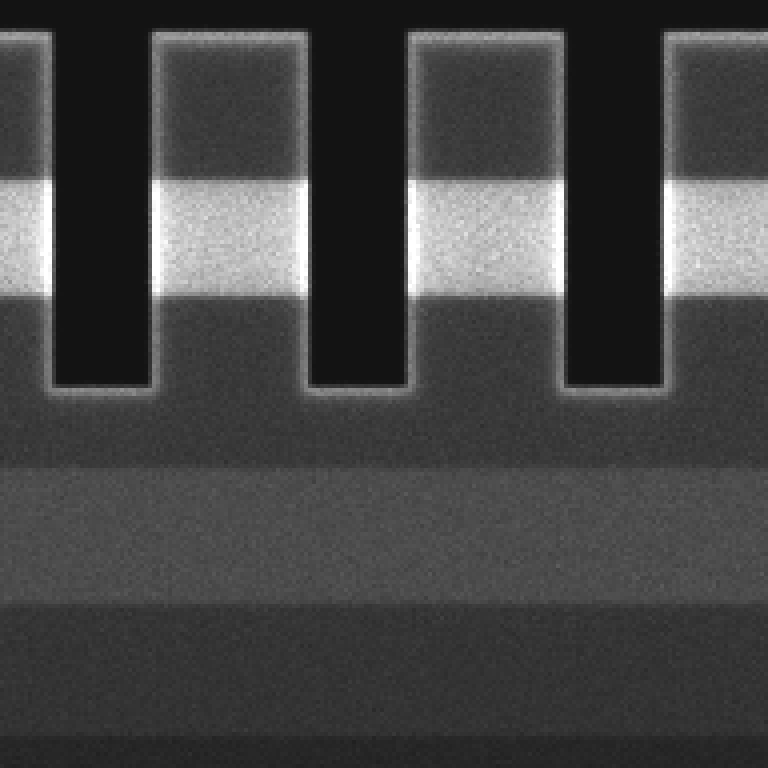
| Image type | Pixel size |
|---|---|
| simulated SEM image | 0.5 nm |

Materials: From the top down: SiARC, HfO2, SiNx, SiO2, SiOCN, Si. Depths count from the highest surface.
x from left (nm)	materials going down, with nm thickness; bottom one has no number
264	SiARC 74, HfO2 58, SiNx 86, SiO2 68, SiOCN 66, Si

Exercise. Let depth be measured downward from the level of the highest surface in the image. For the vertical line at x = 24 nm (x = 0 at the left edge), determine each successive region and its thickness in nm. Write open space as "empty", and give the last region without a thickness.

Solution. SiARC 74, HfO2 58, SiNx 86, SiO2 68, SiOCN 66, Si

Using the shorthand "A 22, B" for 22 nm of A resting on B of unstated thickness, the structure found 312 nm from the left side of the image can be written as empty 178, SiNx 40, SiO2 68, SiOCN 66, Si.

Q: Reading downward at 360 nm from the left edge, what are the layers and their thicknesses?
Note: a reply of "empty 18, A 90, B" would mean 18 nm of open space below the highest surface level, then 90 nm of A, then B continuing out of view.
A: SiARC 74, HfO2 58, SiNx 86, SiO2 68, SiOCN 66, Si